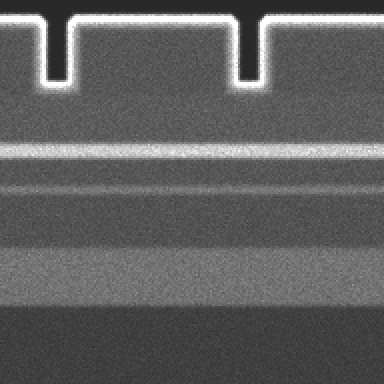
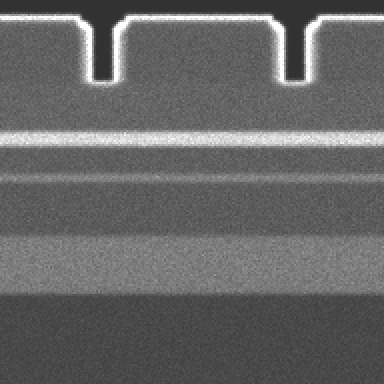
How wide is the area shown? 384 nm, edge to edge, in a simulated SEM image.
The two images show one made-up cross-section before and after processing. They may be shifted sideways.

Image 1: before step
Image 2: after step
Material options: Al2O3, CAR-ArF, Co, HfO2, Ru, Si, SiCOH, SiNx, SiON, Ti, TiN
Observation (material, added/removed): Al2O3, removed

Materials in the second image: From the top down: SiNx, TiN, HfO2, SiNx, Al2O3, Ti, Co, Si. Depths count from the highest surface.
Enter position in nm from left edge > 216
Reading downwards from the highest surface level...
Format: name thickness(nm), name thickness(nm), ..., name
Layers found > SiNx 66, TiN 50, HfO2 14, SiNx 28, Al2O3 8, Ti 54, Co 58, Si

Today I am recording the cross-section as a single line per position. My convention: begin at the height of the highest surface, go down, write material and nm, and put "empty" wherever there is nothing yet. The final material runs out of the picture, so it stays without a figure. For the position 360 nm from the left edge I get SiNx 66, TiN 50, HfO2 14, SiNx 28, Al2O3 8, Ti 54, Co 58, Si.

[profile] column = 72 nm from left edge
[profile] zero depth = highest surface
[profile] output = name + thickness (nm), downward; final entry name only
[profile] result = SiNx 66, TiN 50, HfO2 14, SiNx 28, Al2O3 8, Ti 54, Co 58, Si